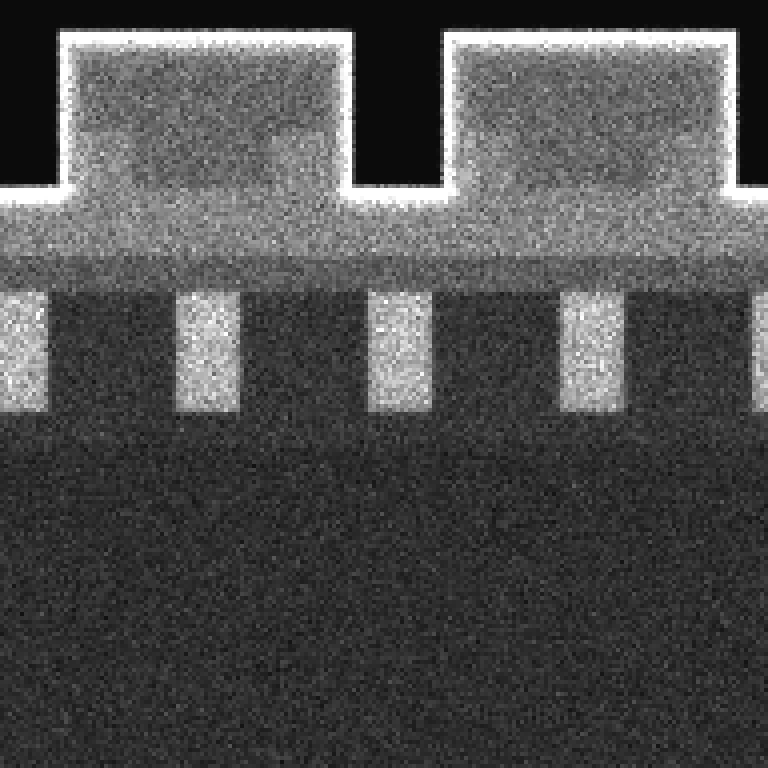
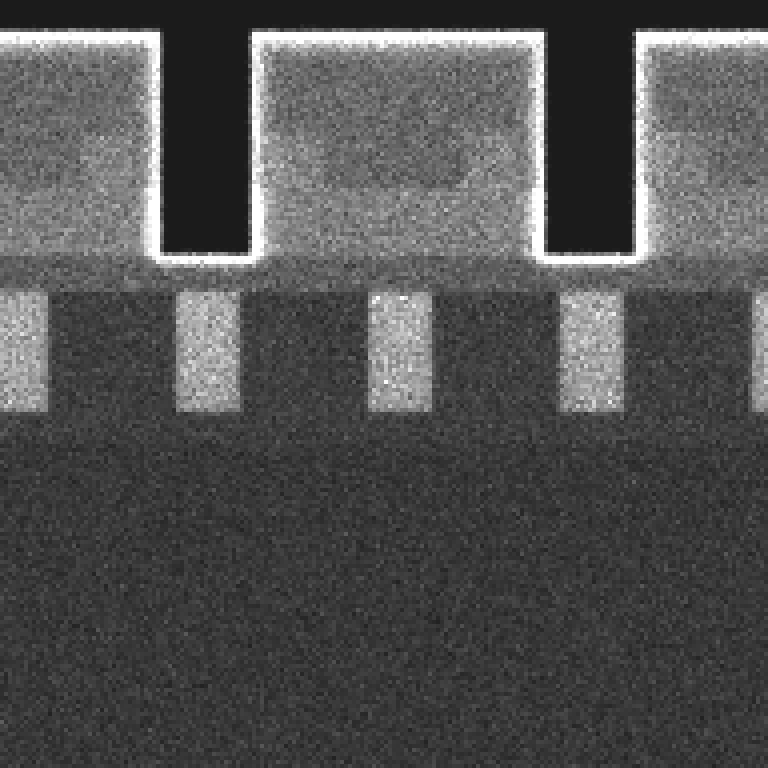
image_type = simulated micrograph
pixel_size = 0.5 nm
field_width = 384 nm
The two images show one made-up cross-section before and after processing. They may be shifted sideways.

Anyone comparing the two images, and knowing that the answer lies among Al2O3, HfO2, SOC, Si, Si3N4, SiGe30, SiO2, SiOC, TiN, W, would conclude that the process removed SiO2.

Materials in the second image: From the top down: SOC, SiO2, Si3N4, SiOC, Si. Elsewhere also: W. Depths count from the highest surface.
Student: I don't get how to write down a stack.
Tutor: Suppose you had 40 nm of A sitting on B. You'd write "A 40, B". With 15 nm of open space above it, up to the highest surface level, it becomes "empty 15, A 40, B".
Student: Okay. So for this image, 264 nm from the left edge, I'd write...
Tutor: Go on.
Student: SOC 78, SiO2 34, Si3N4 18, SiOC 76, Si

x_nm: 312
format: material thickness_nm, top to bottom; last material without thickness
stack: empty 112, Si3N4 18, SiOC 76, Si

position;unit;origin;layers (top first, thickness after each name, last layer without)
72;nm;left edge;SOC 78, SiO2 34, Si3N4 18, SiOC 76, Si